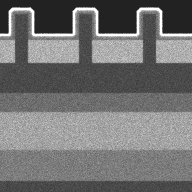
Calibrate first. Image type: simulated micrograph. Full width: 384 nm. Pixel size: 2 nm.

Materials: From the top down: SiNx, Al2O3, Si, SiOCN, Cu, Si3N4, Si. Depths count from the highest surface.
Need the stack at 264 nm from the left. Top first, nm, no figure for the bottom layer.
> empty 52, SiNx 12, Al2O3 46, Si 60, SiOCN 38, Cu 76, Si3N4 62, Si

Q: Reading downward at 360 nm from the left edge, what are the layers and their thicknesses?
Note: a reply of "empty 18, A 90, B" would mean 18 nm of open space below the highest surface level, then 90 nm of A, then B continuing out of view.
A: empty 52, SiNx 12, Al2O3 46, Si 60, SiOCN 38, Cu 76, Si3N4 62, Si